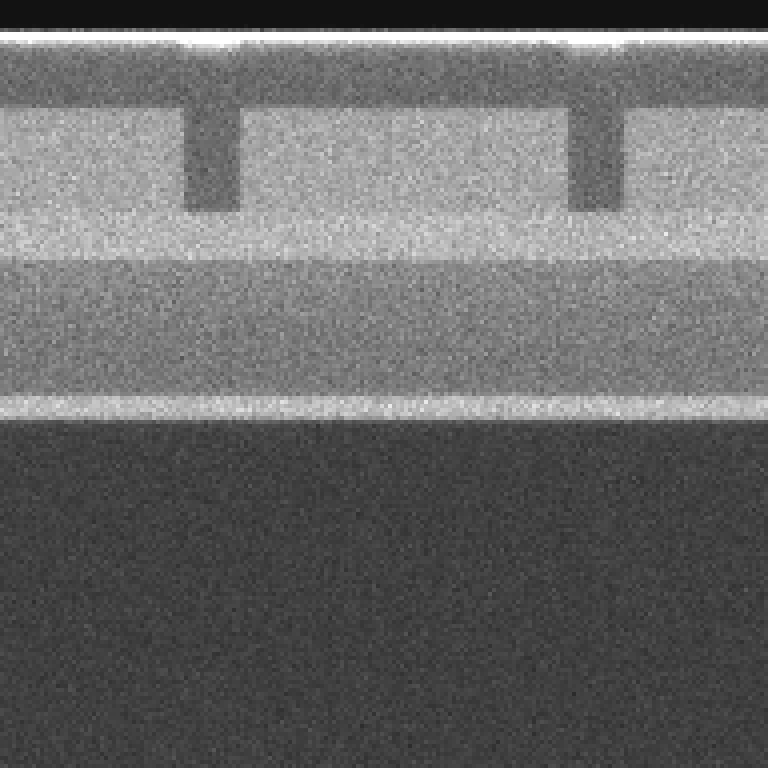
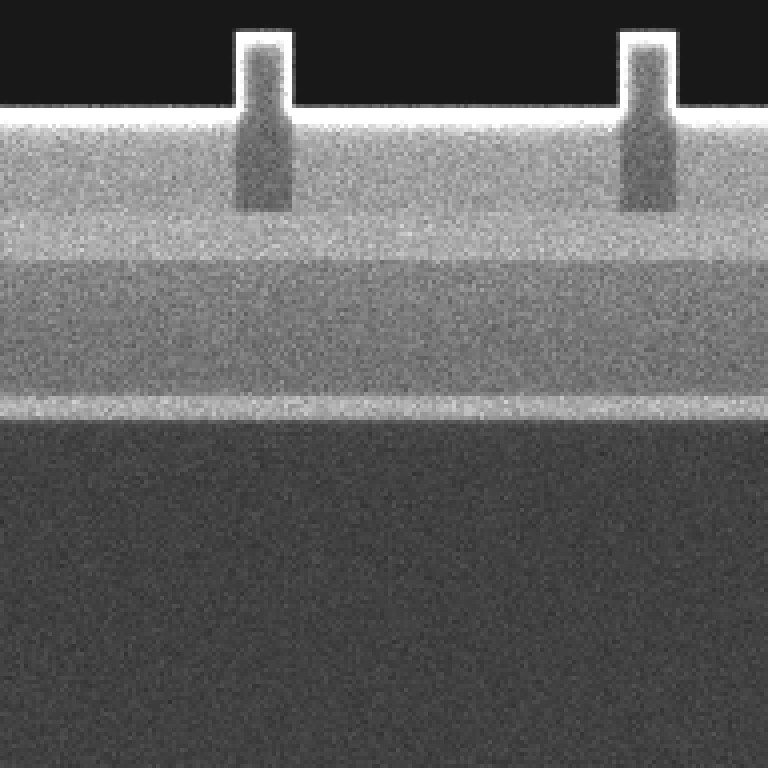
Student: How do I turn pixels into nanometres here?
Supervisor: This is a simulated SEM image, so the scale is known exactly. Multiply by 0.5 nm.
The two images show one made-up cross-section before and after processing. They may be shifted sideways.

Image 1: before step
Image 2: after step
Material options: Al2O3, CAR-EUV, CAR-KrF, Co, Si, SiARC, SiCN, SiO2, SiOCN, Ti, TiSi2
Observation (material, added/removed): SiOCN, removed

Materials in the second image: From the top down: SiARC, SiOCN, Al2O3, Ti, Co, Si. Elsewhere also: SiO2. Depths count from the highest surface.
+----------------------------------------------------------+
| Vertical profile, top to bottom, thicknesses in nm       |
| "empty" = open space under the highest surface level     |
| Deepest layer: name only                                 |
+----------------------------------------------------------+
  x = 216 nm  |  empty 38, SiO2 52, Al2O3 24, Ti 68, Co 12, Si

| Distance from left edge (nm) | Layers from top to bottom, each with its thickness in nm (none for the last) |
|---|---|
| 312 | SiARC 10, SiOCN 80, Al2O3 24, Ti 68, Co 12, Si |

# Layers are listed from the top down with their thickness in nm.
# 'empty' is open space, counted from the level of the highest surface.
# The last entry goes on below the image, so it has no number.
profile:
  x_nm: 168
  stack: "empty 38, SiO2 52, Al2O3 24, Ti 68, Co 12, Si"